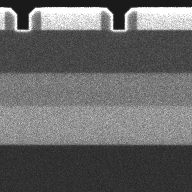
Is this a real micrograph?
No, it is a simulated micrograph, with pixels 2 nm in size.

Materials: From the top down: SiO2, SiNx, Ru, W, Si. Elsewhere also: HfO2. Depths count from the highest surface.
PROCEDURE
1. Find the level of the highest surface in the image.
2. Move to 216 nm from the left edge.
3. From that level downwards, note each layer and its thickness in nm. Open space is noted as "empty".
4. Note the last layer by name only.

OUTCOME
empty 4, SiO2 40, SiNx 86, Ru 66, W 78, Si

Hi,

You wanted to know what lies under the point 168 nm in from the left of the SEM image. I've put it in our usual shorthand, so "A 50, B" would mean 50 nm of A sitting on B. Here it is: HfO2 44, SiNx 86, Ru 66, W 78, Si